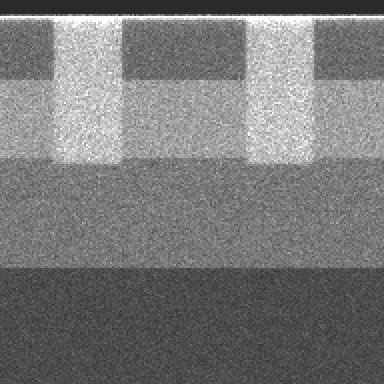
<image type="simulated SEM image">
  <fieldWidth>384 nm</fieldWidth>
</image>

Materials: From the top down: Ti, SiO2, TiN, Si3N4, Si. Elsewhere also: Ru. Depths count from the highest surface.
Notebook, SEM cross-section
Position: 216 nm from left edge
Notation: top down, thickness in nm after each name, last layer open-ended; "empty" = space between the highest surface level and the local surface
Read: Ti 64, SiO2 78, TiN 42, Si3N4 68, Si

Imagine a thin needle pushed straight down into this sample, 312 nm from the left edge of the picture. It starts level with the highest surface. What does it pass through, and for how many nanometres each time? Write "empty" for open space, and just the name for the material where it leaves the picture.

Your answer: Ru 148, TiN 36, Si3N4 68, Si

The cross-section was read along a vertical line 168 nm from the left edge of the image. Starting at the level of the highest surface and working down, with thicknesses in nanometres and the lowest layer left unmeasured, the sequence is Ti 64, SiO2 78, TiN 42, Si3N4 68, Si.